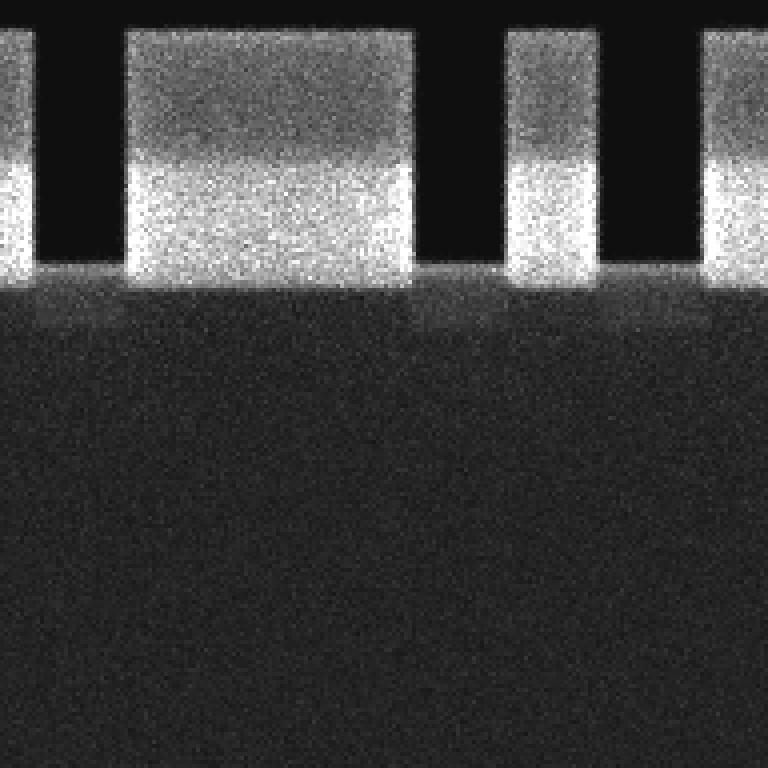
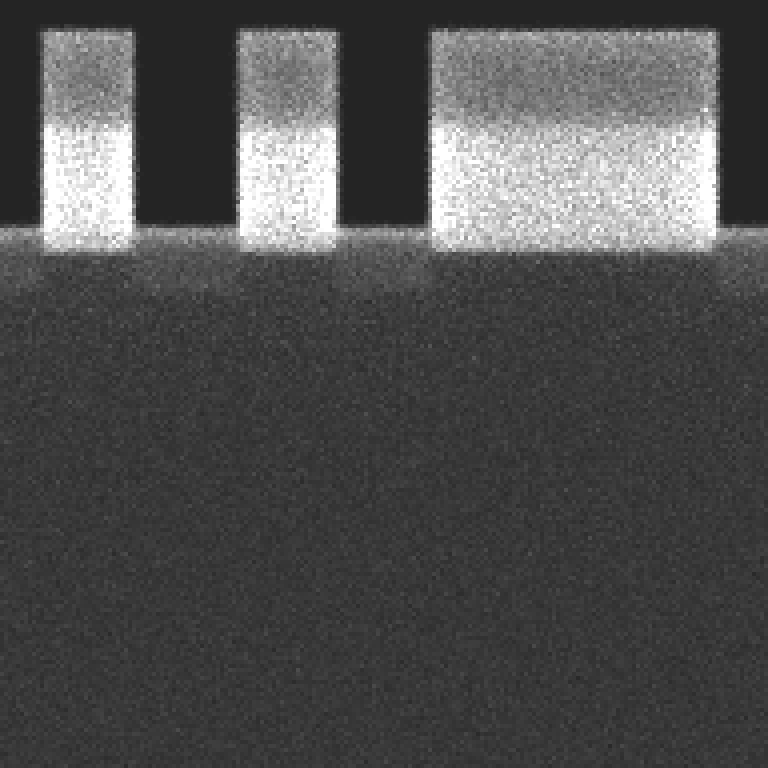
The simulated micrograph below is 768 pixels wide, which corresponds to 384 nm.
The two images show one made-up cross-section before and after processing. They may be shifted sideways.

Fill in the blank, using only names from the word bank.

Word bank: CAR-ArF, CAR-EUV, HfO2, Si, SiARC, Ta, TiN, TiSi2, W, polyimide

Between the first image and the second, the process removed W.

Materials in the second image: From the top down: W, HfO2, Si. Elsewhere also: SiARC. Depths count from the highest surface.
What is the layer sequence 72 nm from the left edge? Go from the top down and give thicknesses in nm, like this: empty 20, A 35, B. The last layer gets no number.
empty 98, SiARC 32, Si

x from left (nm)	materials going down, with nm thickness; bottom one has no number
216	W 48, HfO2 62, Si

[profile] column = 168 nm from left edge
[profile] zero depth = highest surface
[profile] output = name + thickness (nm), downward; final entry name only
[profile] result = empty 98, SiARC 32, Si